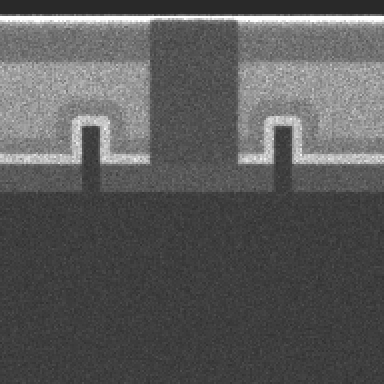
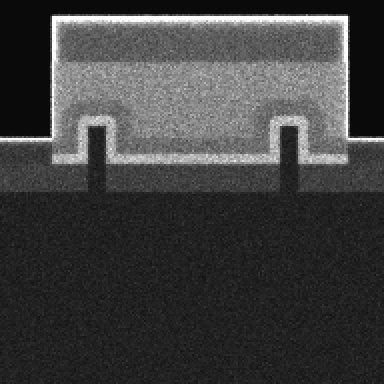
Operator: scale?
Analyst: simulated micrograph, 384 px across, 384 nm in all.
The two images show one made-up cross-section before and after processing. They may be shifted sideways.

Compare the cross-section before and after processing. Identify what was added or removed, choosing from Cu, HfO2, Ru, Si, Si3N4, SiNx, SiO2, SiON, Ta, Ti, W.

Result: SiNx removed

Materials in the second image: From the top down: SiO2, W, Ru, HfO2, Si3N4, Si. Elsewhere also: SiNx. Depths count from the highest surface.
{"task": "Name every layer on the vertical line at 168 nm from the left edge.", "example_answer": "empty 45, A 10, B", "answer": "SiO2 46, W 76, Ru 16, HfO2 10, Si3N4 28, Si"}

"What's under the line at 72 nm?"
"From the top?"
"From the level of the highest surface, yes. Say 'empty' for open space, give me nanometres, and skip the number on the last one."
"SiO2 46, W 40, Ru 52, HfO2 10, Si3N4 28, Si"